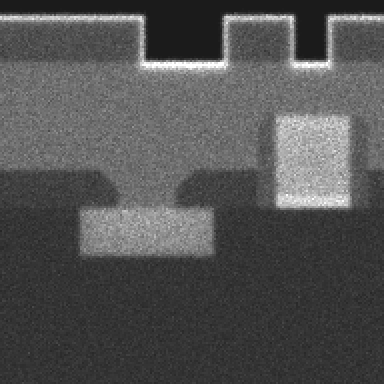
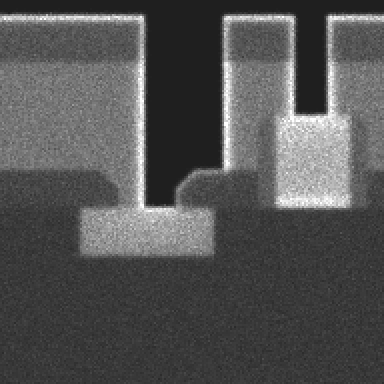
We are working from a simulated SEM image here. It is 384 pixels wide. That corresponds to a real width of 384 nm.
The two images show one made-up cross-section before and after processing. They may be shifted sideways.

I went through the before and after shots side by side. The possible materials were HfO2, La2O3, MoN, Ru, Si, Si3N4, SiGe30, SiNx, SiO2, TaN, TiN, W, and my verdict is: removed, SiO2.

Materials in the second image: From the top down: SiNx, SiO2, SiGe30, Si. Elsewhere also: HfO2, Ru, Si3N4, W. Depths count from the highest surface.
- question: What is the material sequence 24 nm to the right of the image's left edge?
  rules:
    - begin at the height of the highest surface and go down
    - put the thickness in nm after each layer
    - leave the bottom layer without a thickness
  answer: SiNx 46, SiO2 108, SiGe30 38, Si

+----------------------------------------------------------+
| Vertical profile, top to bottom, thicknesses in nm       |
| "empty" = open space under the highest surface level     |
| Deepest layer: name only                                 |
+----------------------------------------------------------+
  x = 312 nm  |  empty 100, W 80, HfO2 12, Si